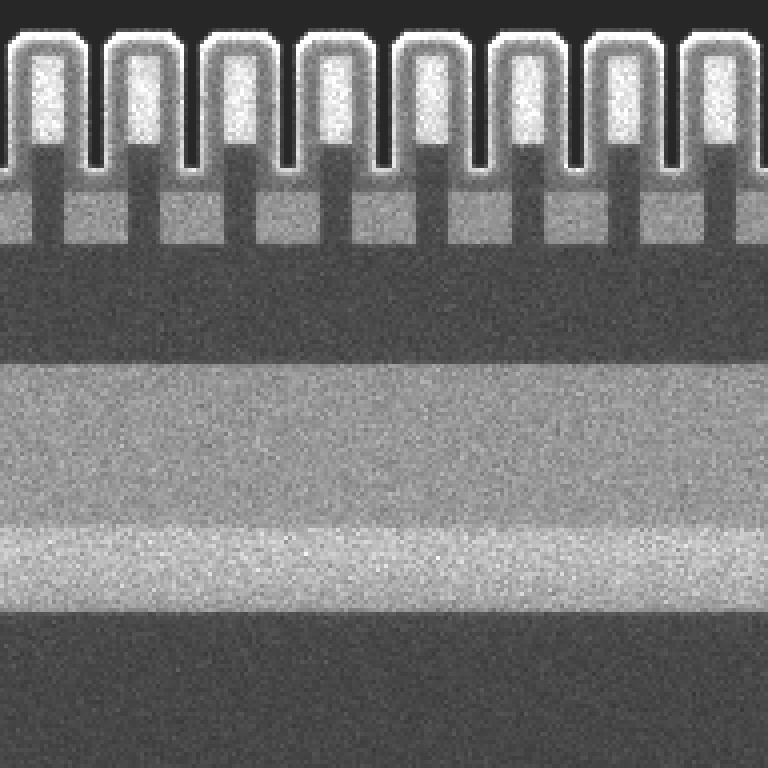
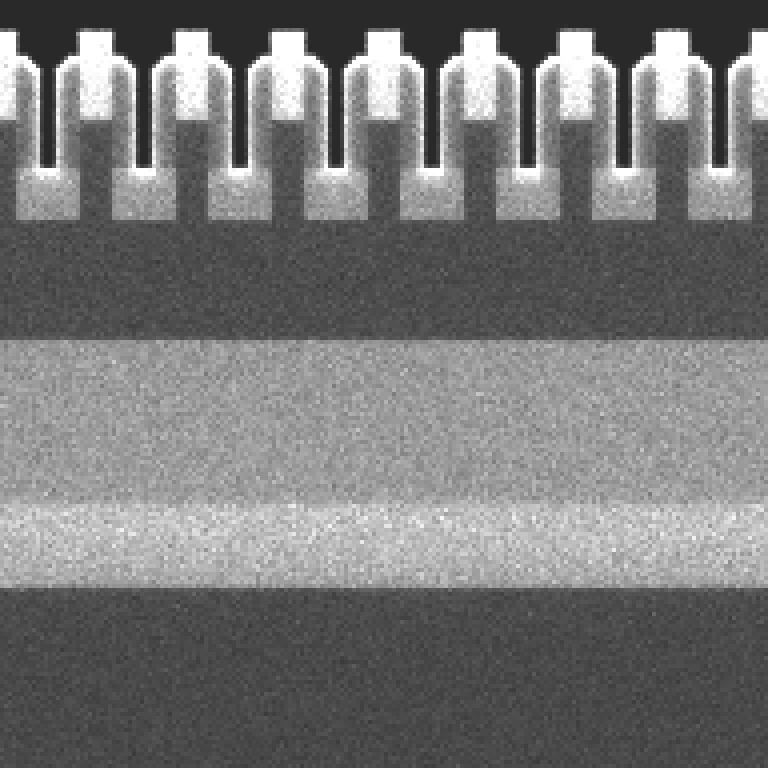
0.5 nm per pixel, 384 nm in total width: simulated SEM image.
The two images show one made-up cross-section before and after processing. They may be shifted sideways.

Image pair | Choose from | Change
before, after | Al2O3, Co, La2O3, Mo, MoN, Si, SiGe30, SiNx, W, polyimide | SiNx (removed)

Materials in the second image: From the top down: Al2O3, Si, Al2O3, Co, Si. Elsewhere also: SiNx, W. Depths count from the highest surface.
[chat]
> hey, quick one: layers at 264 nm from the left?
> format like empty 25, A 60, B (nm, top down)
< empty 68, Al2O3 26, Si 60, Al2O3 82, Co 42, Si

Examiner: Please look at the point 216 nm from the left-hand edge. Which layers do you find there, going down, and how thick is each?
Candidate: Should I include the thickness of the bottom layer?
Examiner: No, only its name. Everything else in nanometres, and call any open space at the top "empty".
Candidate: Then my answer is empty 68, Al2O3 26, Si 60, Al2O3 82, Co 42, Si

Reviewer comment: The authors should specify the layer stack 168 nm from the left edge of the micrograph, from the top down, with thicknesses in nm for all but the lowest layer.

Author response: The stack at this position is empty 68, Al2O3 26, Si 60, Al2O3 82, Co 42, Si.